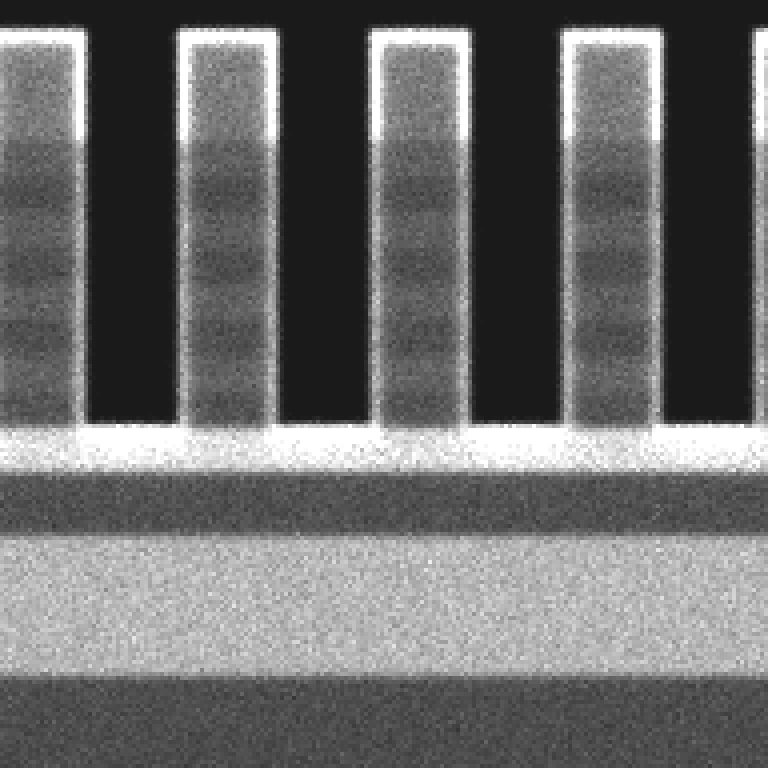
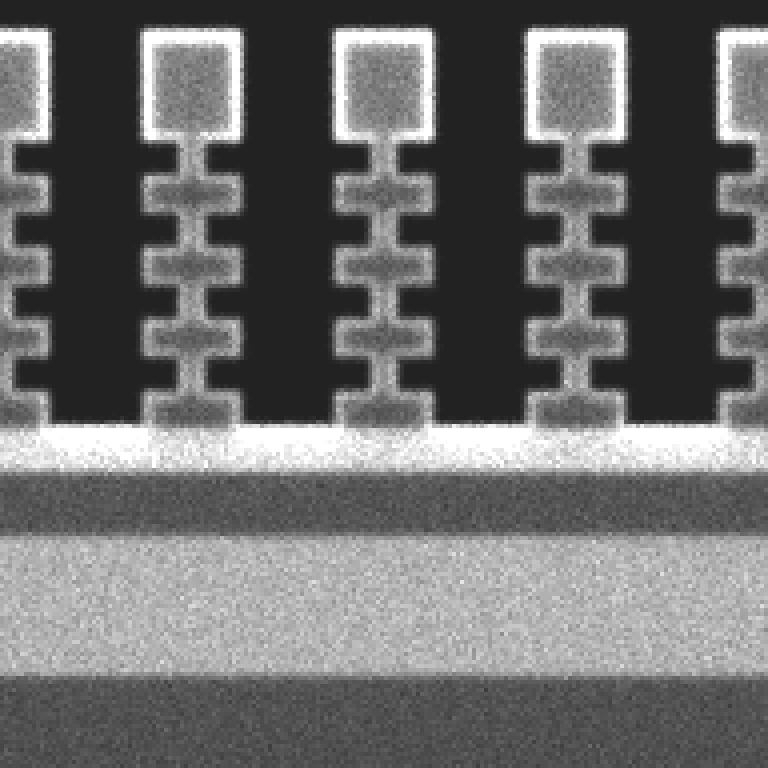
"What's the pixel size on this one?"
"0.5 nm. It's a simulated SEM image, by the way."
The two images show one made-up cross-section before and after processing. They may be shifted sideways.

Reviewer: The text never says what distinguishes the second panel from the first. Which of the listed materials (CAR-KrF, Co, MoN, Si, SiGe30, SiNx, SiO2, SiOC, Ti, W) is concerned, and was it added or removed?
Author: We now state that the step removed SiGe30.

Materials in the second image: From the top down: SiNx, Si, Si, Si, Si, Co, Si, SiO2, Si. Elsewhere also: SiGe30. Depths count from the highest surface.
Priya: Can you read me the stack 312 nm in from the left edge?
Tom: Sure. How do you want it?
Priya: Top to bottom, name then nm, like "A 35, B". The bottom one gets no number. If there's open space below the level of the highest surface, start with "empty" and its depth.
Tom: empty 198, Co 22, Si 32, SiO2 70, Si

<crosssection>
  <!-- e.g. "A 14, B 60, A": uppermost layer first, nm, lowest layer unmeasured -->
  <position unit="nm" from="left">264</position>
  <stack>SiNx 54, empty 18, Si 18, empty 18, Si 18, empty 18, Si 18, empty 18, Si 18, Co 22, Si 32, SiO2 70, Si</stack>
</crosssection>